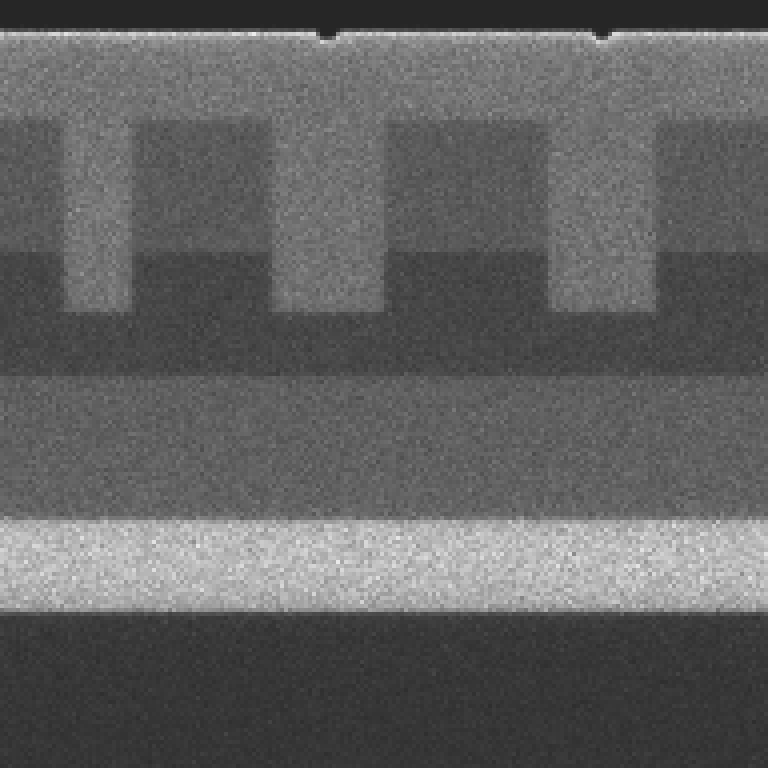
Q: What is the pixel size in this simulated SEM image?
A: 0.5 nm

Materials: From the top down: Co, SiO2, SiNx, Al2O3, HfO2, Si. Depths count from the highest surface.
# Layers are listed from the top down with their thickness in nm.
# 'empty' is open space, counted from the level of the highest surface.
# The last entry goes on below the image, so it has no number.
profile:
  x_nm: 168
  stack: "empty 2, Co 138, SiNx 32, Al2O3 72, HfO2 46, Si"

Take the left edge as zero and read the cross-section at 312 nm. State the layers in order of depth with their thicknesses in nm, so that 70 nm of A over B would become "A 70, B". Co 140, SiNx 32, Al2O3 72, HfO2 46, Si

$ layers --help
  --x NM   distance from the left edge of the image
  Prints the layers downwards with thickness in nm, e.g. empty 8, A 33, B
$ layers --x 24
Co 44, SiO2 66, SiNx 62, Al2O3 72, HfO2 46, Si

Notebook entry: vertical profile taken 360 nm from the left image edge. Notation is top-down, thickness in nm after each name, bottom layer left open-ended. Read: Co 44, SiO2 66, SiNx 62, Al2O3 72, HfO2 46, Si